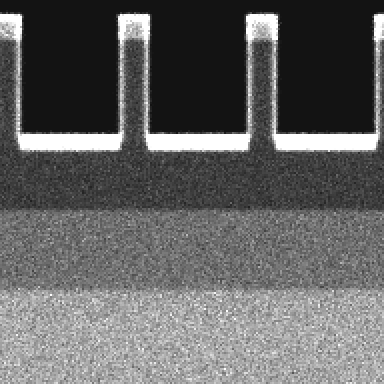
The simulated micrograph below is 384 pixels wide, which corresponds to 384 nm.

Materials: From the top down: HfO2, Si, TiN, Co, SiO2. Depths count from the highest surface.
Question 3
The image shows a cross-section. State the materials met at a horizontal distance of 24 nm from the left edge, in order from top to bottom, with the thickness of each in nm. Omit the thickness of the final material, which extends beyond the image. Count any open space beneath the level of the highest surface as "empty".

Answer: empty 120, HfO2 14, Si 60, TiN 80, Co 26, SiO2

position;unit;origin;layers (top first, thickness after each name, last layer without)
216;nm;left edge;empty 120, HfO2 14, Si 60, TiN 80, Co 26, SiO2